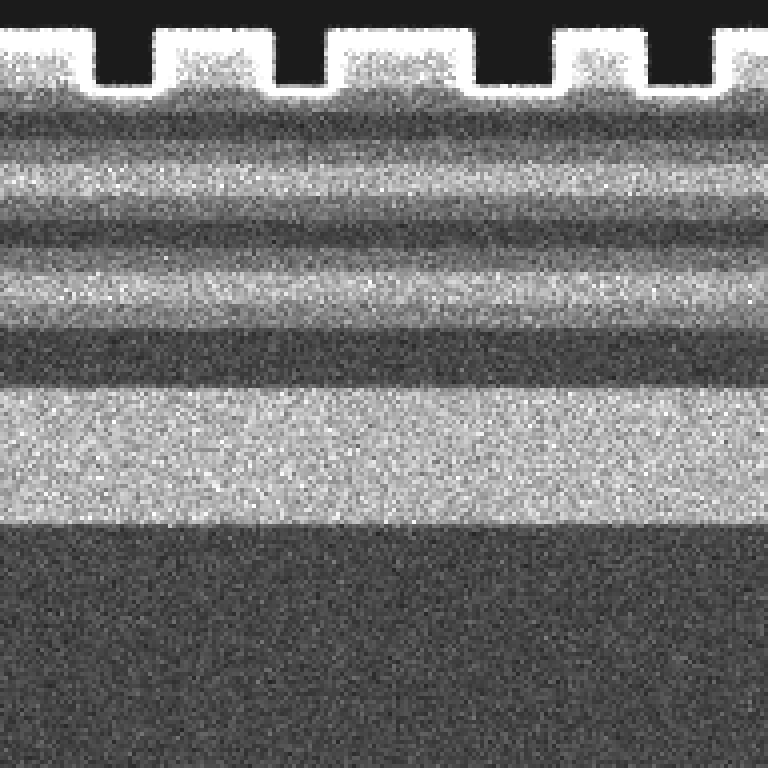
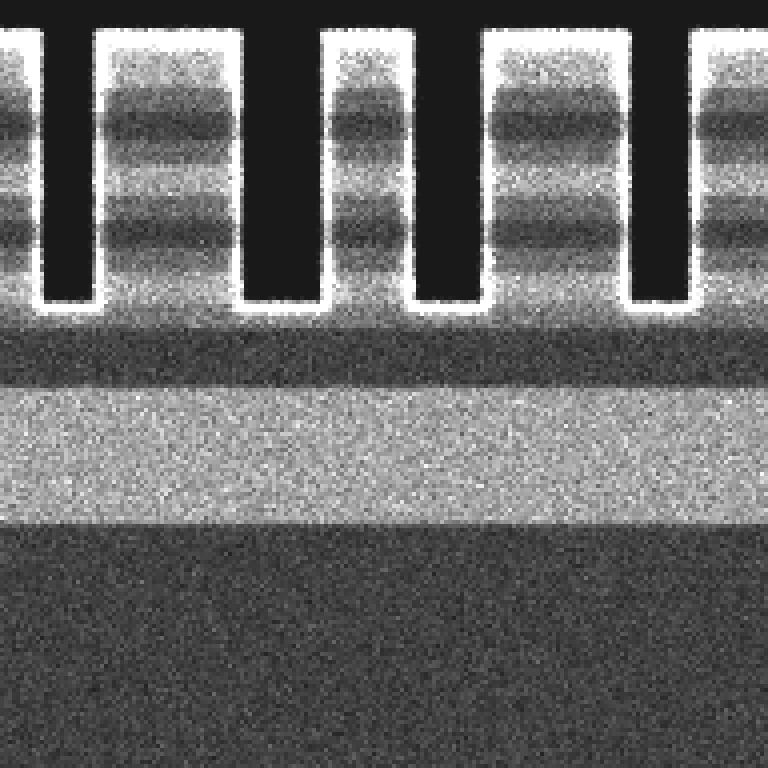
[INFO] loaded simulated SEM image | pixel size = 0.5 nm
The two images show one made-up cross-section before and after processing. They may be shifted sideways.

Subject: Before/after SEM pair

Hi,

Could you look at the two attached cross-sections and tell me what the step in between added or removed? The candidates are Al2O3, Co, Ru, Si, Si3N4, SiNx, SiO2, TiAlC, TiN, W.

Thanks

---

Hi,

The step removed Co and Si and SiNx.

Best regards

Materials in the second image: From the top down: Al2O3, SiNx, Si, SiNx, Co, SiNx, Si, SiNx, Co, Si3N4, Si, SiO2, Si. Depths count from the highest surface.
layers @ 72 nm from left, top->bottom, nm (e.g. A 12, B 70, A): Al2O3 28, SiNx 12, Si 14, SiNx 12, Co 16, SiNx 12, Si 14, SiNx 12, Co 16, Si3N4 12, Si 30, SiO2 68, Si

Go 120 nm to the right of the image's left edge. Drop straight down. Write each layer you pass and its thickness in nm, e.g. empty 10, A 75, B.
empty 136, Si3N4 12, Si 30, SiO2 68, Si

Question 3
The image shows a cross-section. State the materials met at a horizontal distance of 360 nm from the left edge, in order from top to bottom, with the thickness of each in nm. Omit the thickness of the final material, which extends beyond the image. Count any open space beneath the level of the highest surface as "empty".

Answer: Al2O3 28, SiNx 12, Si 14, SiNx 12, Co 16, SiNx 12, Si 14, SiNx 12, Co 16, Si3N4 12, Si 30, SiO2 68, Si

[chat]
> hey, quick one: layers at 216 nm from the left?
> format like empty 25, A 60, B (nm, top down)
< empty 136, Si3N4 12, Si 30, SiO2 68, Si